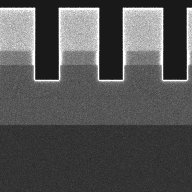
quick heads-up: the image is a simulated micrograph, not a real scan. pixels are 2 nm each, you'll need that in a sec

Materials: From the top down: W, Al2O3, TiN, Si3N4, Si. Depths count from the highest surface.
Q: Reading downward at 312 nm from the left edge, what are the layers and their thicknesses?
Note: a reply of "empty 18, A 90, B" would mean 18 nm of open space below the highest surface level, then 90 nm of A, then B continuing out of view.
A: W 86, Al2O3 28, TiN 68, Si3N4 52, Si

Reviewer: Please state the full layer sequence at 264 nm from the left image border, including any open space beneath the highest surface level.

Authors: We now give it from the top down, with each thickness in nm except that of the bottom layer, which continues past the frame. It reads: W 86, Al2O3 28, TiN 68, Si3N4 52, Si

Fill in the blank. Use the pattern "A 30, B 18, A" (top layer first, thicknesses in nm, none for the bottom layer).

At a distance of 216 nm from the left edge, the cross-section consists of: empty 144, TiN 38, Si3N4 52, Si